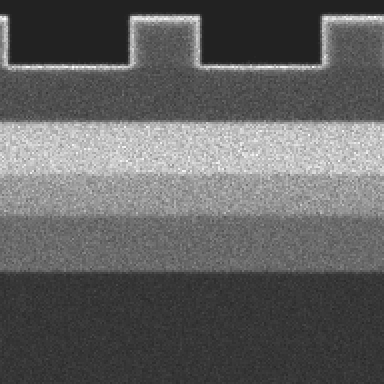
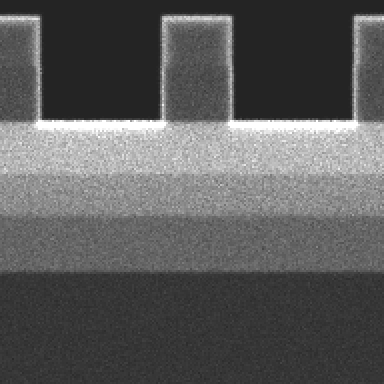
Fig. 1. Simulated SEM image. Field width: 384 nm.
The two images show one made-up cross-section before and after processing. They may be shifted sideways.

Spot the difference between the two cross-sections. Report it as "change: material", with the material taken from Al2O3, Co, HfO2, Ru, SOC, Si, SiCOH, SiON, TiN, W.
removed: TiN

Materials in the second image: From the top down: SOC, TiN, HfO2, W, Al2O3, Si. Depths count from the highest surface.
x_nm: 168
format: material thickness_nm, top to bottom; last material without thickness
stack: SOC 50, TiN 56, HfO2 52, W 42, Al2O3 56, Si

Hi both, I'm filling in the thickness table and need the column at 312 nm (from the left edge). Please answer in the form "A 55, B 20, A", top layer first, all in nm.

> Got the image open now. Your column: empty 106, HfO2 52, W 42, Al2O3 56, Si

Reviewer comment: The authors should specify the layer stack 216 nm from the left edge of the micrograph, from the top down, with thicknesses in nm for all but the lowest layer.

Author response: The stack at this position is SOC 50, TiN 56, HfO2 52, W 42, Al2O3 56, Si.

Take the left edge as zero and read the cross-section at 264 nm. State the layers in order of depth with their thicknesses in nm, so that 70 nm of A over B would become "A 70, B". empty 106, HfO2 52, W 42, Al2O3 56, Si